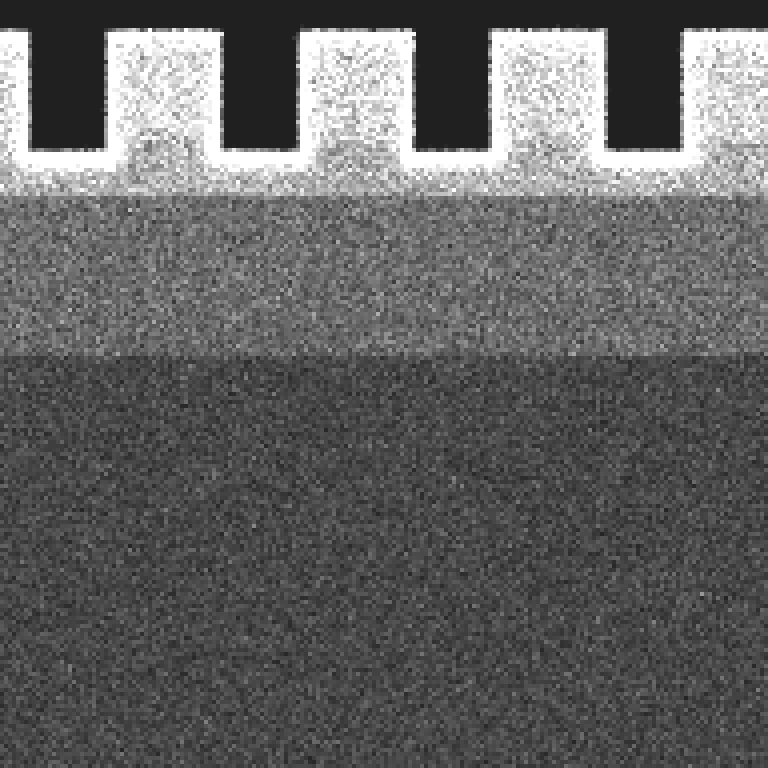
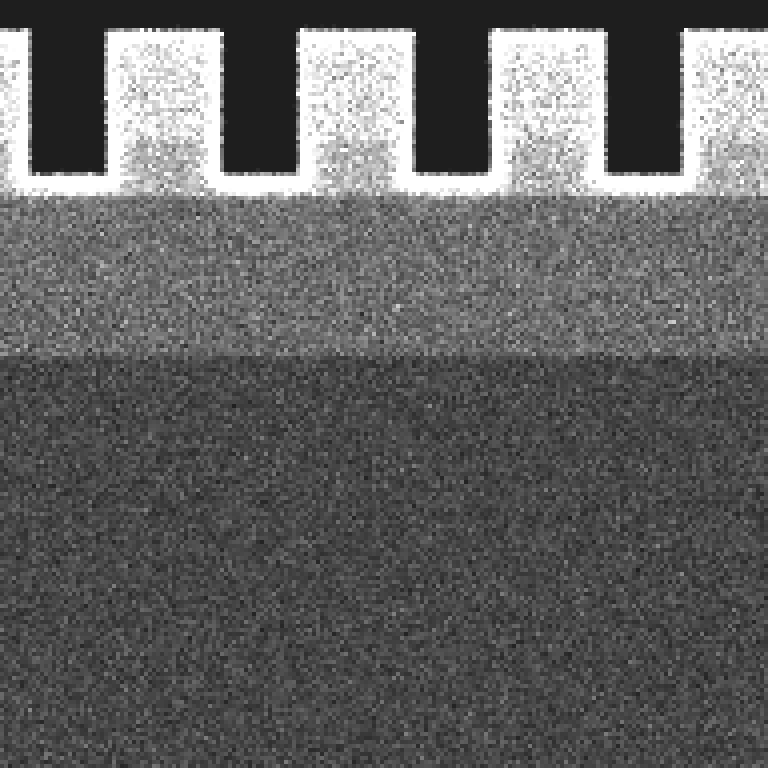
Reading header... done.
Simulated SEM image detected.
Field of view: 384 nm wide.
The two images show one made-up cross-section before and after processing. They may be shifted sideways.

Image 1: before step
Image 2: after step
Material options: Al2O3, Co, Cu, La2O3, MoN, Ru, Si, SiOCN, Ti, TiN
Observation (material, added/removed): Al2O3, removed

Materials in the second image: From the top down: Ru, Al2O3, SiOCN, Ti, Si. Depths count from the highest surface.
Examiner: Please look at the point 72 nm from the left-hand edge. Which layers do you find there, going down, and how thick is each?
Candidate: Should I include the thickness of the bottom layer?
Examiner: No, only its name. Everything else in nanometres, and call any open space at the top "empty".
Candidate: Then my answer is Ru 54, Al2O3 28, SiOCN 46, Ti 34, Si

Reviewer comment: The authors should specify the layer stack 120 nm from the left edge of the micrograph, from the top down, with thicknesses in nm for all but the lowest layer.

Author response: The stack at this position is empty 72, Al2O3 10, SiOCN 46, Ti 34, Si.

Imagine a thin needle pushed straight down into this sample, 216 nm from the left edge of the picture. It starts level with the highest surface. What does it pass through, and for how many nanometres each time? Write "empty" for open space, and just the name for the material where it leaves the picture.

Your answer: empty 72, Al2O3 10, SiOCN 46, Ti 34, Si